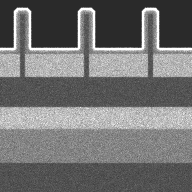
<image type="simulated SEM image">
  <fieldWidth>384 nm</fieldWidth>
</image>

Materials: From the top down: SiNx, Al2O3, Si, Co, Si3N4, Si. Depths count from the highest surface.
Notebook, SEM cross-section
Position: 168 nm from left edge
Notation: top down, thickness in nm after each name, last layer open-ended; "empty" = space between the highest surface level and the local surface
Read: SiNx 12, Si 186, Co 44, Si3N4 68, Si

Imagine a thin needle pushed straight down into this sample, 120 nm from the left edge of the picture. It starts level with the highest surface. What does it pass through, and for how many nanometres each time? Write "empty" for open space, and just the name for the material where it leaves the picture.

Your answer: empty 80, SiNx 12, Al2O3 46, Si 60, Co 44, Si3N4 68, Si